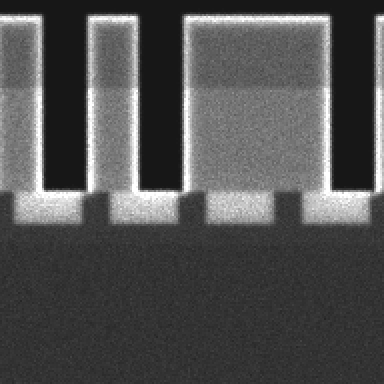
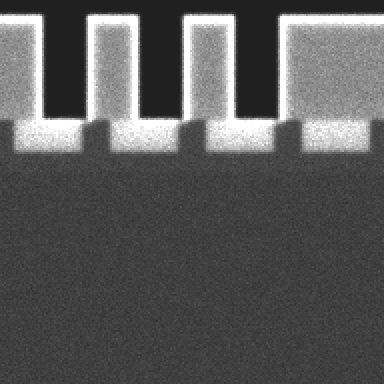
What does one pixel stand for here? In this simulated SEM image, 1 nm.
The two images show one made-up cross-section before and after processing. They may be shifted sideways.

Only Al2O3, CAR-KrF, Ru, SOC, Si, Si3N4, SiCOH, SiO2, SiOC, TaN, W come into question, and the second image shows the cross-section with SOC removed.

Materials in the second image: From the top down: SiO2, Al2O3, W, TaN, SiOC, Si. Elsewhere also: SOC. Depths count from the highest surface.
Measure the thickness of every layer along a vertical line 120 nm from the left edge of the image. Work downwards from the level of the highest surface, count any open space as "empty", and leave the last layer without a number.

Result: SiO2 84, Al2O3 20, W 26, TaN 6, SiOC 20, Si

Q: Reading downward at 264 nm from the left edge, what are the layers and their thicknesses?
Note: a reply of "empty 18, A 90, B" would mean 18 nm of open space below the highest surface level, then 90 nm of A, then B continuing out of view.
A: empty 104, W 26, TaN 6, SiOC 20, Si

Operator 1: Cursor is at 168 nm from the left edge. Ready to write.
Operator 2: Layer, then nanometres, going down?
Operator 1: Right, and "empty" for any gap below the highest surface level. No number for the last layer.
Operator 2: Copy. empty 104, W 26, TaN 6, SiOC 20, Si